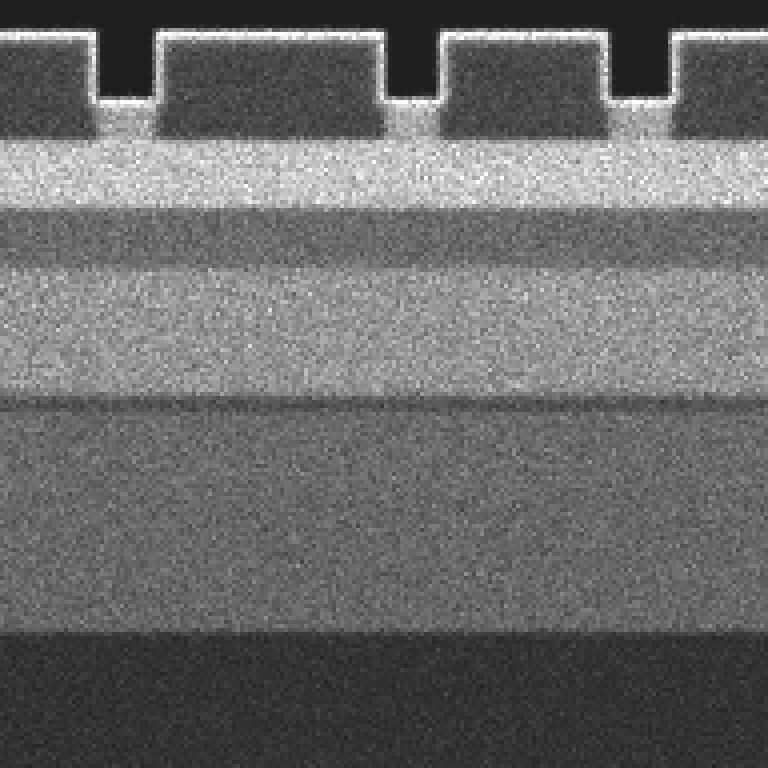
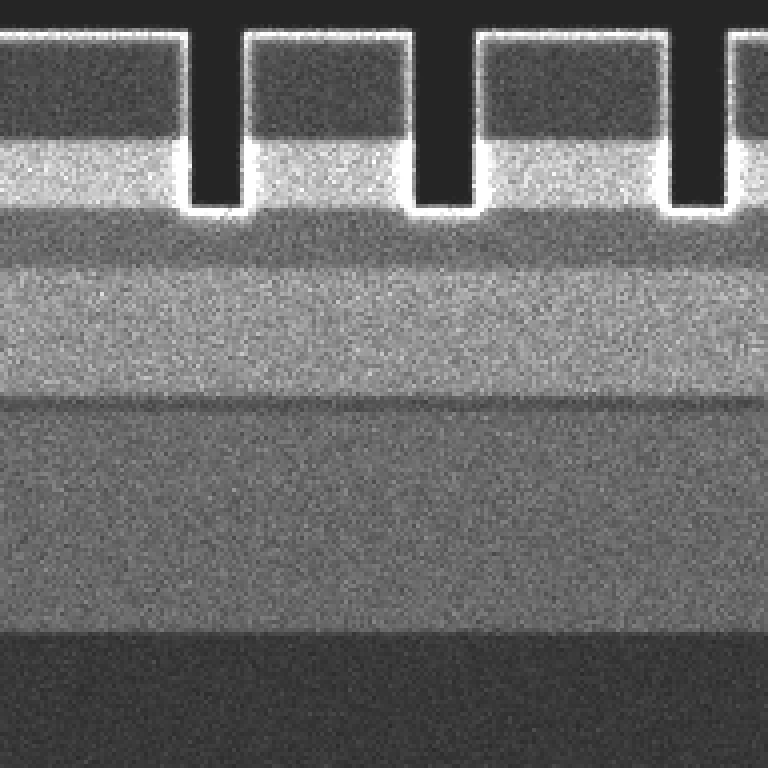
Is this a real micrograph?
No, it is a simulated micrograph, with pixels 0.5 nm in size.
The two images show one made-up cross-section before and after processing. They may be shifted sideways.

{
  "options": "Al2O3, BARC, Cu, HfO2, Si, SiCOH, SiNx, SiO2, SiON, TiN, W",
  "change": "removed",
  "material": "HfO2 and W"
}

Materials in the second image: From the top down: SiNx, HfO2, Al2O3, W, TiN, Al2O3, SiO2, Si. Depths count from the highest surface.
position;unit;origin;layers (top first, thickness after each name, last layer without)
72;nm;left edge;SiNx 54, HfO2 34, Al2O3 30, W 64, TiN 8, Al2O3 40, SiO2 70, Si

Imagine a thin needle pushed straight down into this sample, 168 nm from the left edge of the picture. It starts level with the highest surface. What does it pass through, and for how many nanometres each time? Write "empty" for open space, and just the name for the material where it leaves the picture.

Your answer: SiNx 54, HfO2 34, Al2O3 30, W 64, TiN 8, Al2O3 40, SiO2 70, Si